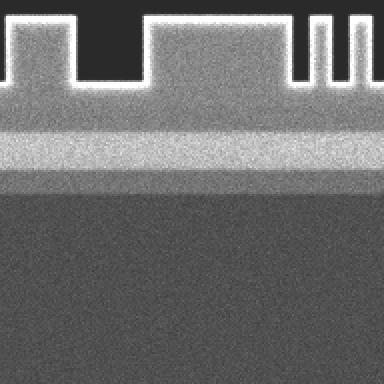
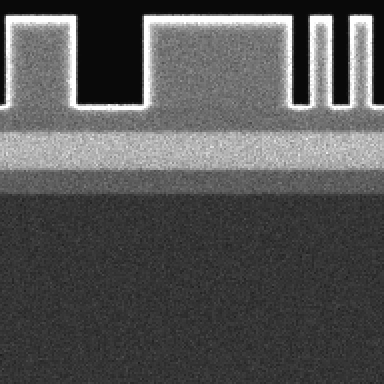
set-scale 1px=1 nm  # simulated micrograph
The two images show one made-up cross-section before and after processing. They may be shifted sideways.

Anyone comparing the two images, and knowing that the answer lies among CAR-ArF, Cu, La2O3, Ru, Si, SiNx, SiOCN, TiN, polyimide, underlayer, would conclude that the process removed underlayer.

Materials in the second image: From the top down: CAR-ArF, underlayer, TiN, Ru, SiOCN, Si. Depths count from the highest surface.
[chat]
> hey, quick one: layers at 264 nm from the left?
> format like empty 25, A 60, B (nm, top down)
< CAR-ArF 66, underlayer 24, TiN 26, Ru 38, SiOCN 24, Si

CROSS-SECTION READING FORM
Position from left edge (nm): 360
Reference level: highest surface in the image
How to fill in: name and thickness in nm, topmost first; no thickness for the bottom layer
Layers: CAR-ArF 66, underlayer 24, TiN 26, Ru 38, SiOCN 24, Si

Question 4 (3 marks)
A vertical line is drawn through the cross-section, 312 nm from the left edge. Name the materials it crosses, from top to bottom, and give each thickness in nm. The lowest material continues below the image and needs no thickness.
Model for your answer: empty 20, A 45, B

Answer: CAR-ArF 66, underlayer 24, TiN 26, Ru 38, SiOCN 24, Si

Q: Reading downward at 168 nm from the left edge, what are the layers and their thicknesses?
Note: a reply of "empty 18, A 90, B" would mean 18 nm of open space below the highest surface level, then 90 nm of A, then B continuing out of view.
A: CAR-ArF 66, underlayer 24, TiN 26, Ru 38, SiOCN 24, Si